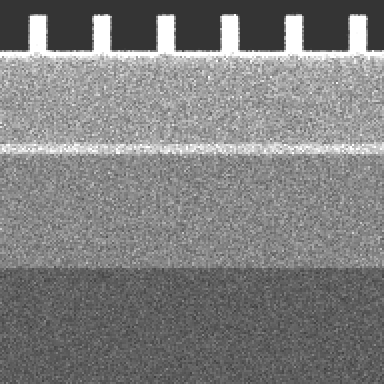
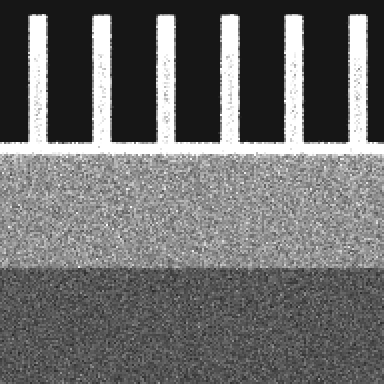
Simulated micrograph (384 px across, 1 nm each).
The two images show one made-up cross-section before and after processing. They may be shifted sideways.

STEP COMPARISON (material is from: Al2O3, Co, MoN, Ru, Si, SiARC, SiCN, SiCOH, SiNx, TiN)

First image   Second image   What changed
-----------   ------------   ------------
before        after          TiN, removed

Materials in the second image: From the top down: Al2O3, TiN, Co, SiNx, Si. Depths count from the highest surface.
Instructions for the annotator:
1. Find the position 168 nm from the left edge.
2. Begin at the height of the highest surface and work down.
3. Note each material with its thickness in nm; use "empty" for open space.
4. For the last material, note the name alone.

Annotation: Al2O3 36, TiN 92, Co 10, SiNx 114, Si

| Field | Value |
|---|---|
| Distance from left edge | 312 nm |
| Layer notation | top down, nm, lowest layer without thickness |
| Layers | empty 128, Co 10, SiNx 114, Si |